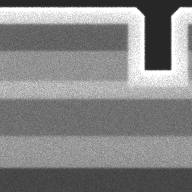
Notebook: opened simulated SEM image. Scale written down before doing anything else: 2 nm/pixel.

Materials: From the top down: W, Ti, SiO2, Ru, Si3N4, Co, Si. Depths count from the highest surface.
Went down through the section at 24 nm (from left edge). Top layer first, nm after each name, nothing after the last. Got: W 32, Ti 54, SiO2 60, Ru 36, Si3N4 74, Co 64, Si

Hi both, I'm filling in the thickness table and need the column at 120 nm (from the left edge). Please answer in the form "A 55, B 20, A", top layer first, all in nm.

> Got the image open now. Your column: W 32, Ti 54, SiO2 60, Ru 36, Si3N4 74, Co 64, Si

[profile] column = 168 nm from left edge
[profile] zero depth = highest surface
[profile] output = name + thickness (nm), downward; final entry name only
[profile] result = W 32, Ti 54, SiO2 60, Ru 36, Si3N4 74, Co 64, Si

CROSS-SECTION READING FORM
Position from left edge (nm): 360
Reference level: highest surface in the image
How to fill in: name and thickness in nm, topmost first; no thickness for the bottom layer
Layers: W 158, Ru 24, Si3N4 74, Co 64, Si